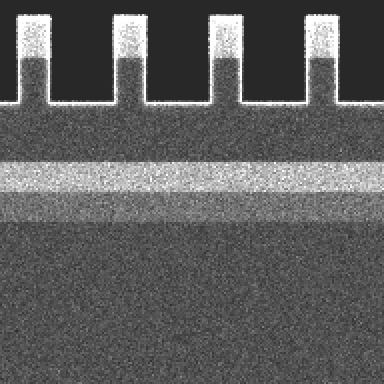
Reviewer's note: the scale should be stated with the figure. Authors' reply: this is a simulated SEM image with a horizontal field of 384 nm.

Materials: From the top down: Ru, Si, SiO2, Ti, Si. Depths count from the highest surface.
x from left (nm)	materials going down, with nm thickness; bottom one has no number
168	empty 86, Si 60, SiO2 30, Ti 30, Si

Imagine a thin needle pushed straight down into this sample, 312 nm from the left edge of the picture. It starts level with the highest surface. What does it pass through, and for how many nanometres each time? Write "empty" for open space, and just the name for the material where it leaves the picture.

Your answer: Ru 42, Si 104, SiO2 30, Ti 30, Si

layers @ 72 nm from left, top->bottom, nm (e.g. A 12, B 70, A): empty 86, Si 60, SiO2 30, Ti 30, Si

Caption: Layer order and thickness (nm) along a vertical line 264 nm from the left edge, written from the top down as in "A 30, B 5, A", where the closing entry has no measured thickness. empty 86, Si 60, SiO2 30, Ti 30, Si